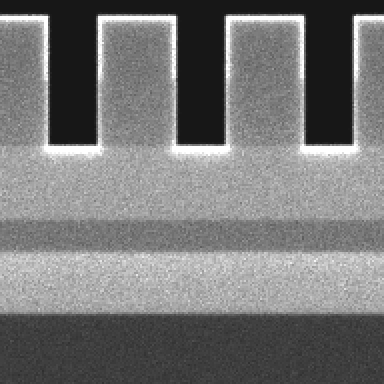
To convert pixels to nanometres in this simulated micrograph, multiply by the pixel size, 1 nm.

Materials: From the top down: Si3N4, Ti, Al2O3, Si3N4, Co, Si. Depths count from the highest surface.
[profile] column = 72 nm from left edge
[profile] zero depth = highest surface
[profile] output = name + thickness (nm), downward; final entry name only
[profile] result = empty 130, Al2O3 74, Si3N4 32, Co 62, Si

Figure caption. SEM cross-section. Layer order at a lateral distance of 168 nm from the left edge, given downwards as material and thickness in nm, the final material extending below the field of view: Si3N4 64, Ti 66, Al2O3 74, Si3N4 32, Co 62, Si